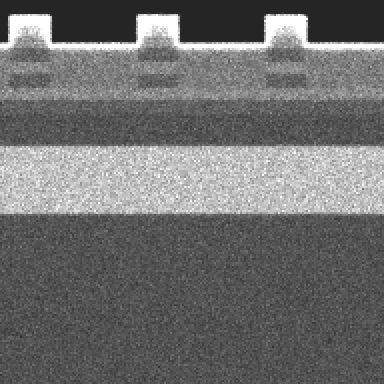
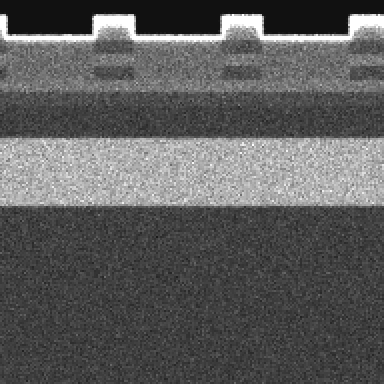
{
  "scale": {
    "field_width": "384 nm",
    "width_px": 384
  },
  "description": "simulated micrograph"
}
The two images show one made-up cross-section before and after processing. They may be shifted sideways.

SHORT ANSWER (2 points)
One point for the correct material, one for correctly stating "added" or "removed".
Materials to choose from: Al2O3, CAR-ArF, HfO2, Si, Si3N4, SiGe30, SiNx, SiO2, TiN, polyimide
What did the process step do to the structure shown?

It removed Al2O3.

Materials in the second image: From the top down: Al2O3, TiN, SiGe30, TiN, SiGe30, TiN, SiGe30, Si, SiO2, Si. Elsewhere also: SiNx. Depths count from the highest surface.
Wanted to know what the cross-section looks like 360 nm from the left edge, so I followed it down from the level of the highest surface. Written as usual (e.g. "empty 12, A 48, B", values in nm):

Al2O3 12, TiN 12, SiGe30 14, TiN 12, SiGe30 14, TiN 12, SiGe30 14, Si 32, SiO2 68, Si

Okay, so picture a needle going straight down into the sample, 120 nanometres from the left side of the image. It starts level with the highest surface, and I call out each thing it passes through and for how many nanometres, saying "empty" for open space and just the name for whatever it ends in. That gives Al2O3 12, TiN 12, SiGe30 14, TiN 12, SiGe30 14, TiN 12, SiGe30 14, Si 32, SiO2 68, Si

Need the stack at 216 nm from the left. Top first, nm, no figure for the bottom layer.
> empty 20, SiNx 44, TiN 12, SiGe30 14, Si 32, SiO2 68, Si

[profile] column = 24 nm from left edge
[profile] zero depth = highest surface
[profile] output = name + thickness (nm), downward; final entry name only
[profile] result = empty 20, SiNx 44, TiN 12, SiGe30 14, Si 32, SiO2 68, Si